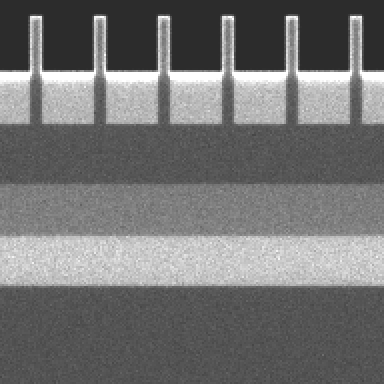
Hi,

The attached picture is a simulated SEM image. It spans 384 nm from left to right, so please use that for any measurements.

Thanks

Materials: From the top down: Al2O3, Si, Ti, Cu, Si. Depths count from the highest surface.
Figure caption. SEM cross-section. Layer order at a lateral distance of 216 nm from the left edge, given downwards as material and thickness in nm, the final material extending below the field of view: empty 56, Al2O3 52, Si 60, Ti 52, Cu 50, Si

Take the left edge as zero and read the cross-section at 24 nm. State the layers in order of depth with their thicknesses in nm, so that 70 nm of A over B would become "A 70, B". empty 56, Al2O3 52, Si 60, Ti 52, Cu 50, Si